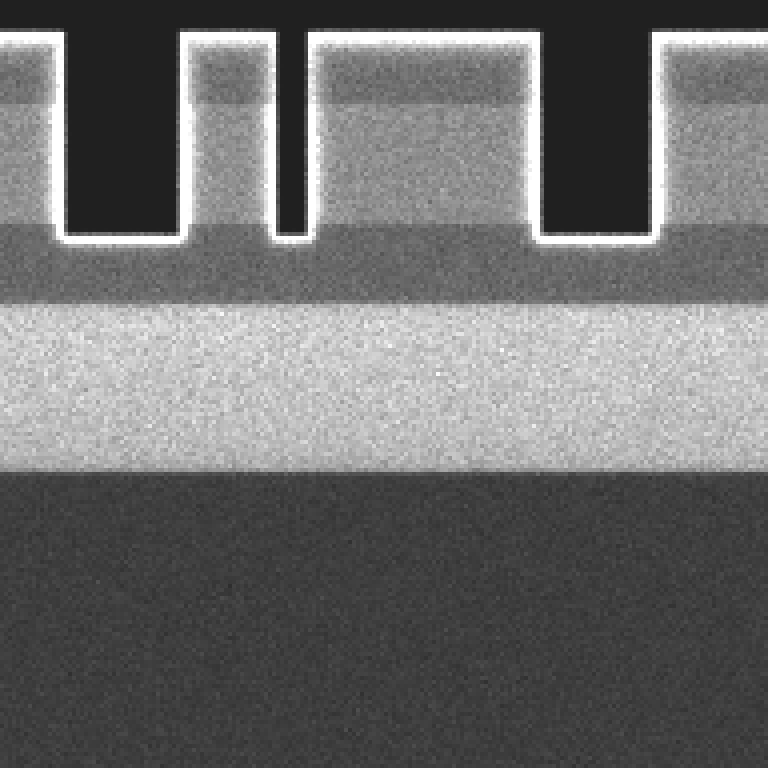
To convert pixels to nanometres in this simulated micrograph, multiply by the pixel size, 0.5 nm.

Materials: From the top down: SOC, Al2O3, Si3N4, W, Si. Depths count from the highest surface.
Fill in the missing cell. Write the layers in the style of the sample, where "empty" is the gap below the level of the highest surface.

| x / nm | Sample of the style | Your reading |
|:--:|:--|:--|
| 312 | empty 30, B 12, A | empty 102, Si3N4 34, W 84, Si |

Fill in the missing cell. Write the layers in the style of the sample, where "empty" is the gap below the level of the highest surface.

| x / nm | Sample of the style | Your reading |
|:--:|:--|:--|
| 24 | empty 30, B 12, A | SOC 36, Al2O3 60, Si3N4 40, W 84, Si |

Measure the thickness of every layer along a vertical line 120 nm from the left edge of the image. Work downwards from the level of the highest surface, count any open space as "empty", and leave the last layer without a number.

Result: SOC 36, Al2O3 60, Si3N4 40, W 84, Si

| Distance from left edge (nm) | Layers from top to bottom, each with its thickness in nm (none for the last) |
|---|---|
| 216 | SOC 36, Al2O3 60, Si3N4 40, W 84, Si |